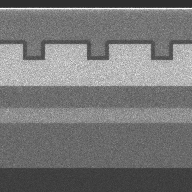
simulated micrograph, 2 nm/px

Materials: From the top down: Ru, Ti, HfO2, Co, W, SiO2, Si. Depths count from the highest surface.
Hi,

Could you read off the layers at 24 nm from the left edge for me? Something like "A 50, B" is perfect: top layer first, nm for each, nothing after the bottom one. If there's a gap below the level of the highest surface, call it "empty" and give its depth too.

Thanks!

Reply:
Ru 64, Ti 8, HfO2 84, Co 44, W 30, SiO2 90, Si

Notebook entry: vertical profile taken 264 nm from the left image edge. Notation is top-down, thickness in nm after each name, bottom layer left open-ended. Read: Ru 64, Ti 8, HfO2 84, Co 44, W 30, SiO2 90, Si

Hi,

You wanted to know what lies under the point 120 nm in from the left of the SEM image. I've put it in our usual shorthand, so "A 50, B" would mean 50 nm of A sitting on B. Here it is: Ru 64, Ti 8, HfO2 84, Co 44, W 30, SiO2 90, Si